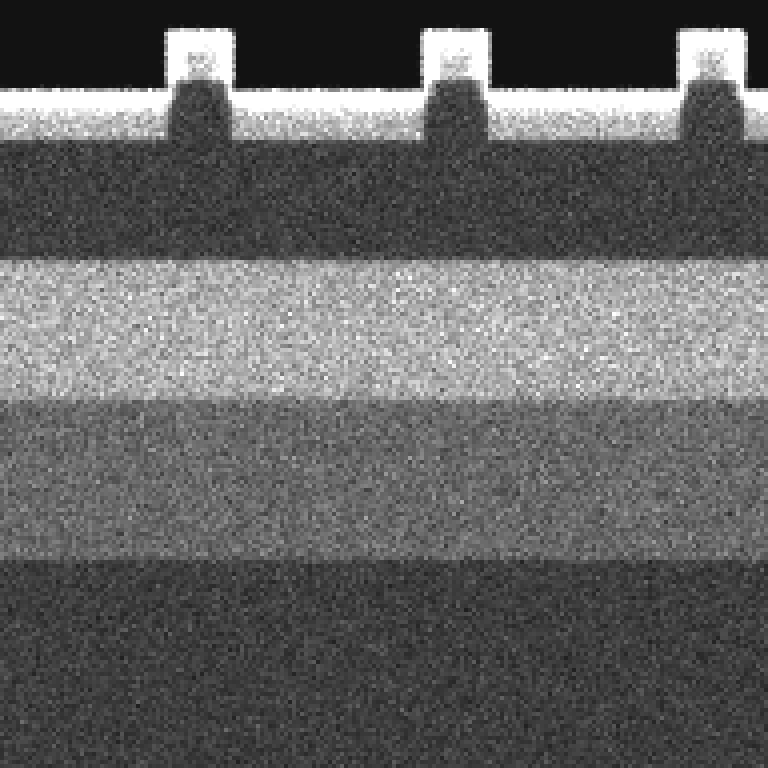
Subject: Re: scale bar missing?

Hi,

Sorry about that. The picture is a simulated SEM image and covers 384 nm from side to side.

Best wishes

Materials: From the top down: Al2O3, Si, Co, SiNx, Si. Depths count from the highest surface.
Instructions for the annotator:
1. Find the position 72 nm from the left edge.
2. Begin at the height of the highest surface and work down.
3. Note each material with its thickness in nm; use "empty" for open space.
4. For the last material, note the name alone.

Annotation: empty 30, Al2O3 24, Si 60, Co 70, SiNx 80, Si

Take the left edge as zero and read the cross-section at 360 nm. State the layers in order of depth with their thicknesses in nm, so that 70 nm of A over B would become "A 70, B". Al2O3 24, Si 90, Co 70, SiNx 80, Si